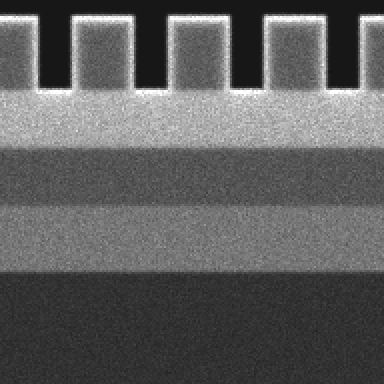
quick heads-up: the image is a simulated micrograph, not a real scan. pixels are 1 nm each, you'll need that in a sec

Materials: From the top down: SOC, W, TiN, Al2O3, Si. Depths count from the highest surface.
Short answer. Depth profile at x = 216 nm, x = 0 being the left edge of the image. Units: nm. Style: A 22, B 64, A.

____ SOC 74, W 58, TiN 58, Al2O3 66, Si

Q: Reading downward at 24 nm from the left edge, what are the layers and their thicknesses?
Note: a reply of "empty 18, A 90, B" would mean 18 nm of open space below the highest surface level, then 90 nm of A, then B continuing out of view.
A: SOC 74, W 58, TiN 58, Al2O3 66, Si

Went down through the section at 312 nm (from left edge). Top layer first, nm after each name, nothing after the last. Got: SOC 74, W 58, TiN 58, Al2O3 66, Si